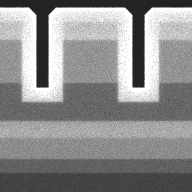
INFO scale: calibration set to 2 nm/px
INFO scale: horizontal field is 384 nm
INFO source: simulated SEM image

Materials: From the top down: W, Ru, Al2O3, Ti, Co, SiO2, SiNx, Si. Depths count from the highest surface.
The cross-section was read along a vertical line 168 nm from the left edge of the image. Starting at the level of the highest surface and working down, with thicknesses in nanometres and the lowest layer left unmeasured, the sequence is W 28, Ru 36, Al2O3 86, Ti 76, Co 34, SiO2 42, SiNx 28, Si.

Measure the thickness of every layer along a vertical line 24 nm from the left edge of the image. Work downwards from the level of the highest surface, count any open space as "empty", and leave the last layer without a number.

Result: W 28, Ru 36, Al2O3 86, Ti 76, Co 34, SiO2 42, SiNx 28, Si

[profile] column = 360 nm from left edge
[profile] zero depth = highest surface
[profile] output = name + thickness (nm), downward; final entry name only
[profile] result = W 28, Ru 36, Al2O3 86, Ti 76, Co 34, SiO2 42, SiNx 28, Si